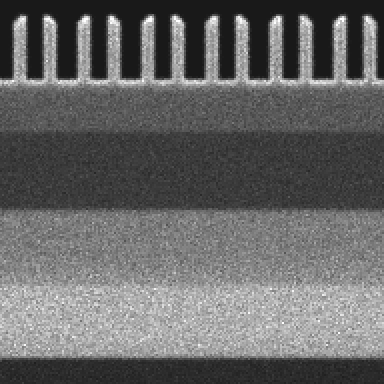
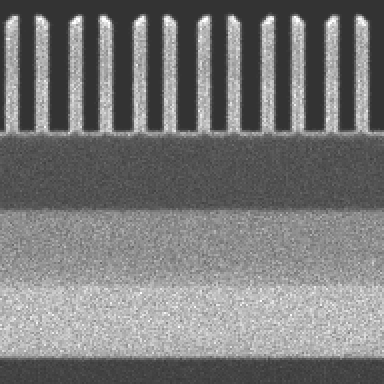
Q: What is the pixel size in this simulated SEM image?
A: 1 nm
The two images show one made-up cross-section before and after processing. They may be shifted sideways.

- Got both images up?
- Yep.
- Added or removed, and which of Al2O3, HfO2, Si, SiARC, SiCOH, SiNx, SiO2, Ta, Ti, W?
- removed, Al2O3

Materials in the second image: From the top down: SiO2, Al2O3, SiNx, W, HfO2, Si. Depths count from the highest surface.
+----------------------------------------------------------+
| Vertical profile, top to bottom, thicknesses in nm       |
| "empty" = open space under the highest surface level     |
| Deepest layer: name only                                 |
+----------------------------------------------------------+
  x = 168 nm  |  SiO2 64, Al2O3 52, SiNx 78, W 76, HfO2 72, Si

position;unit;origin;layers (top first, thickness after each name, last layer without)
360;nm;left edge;SiO2 64, Al2O3 52, SiNx 78, W 76, HfO2 72, Si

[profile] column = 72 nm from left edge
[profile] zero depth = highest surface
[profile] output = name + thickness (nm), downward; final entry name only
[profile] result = empty 4, SiO2 60, Al2O3 52, SiNx 78, W 76, HfO2 72, Si